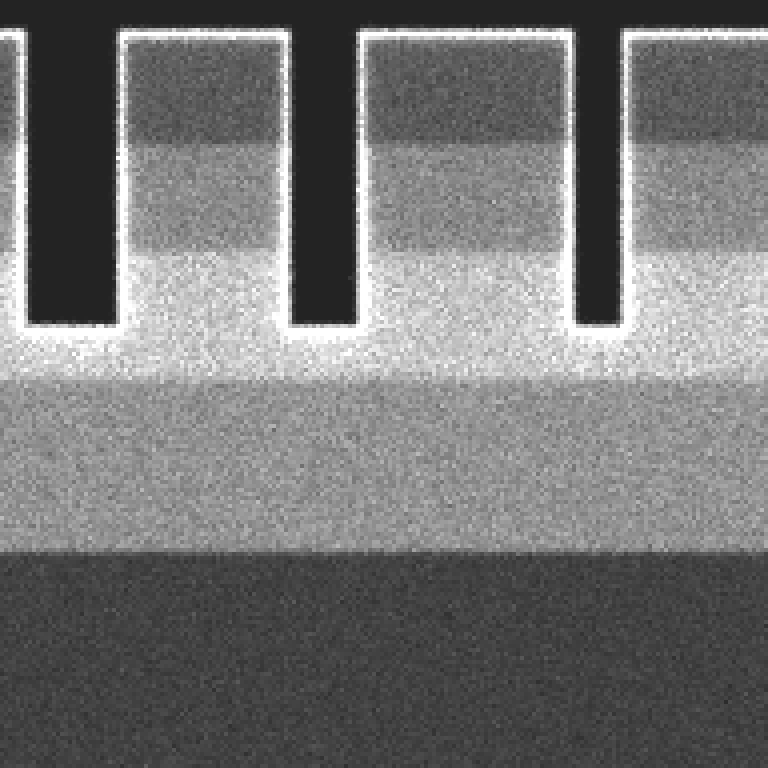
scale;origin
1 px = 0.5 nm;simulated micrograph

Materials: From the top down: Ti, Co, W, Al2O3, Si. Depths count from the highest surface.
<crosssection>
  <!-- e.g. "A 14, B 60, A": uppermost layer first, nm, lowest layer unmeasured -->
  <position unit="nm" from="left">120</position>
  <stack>Ti 56, Co 54, W 64, Al2O3 86, Si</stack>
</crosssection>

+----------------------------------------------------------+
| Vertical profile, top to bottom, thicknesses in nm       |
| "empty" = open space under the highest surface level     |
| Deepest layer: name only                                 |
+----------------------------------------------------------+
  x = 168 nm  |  empty 148, W 26, Al2O3 86, Si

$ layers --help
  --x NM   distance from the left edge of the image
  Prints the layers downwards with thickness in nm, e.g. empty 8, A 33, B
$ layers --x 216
Ti 56, Co 54, W 64, Al2O3 86, Si